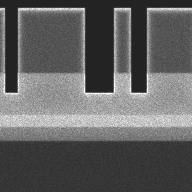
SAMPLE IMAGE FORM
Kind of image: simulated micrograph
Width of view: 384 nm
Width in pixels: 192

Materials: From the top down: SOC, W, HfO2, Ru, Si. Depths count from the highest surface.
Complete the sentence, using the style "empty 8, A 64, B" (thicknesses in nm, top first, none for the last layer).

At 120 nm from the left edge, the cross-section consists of SOC 130, W 84, HfO2 24, Ru 28, Si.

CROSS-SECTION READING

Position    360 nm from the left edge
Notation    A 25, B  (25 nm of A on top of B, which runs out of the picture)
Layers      SOC 130, W 84, HfO2 24, Ru 28, Si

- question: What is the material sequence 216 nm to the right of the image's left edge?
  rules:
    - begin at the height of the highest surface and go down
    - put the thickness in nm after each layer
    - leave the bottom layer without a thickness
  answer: empty 170, W 44, HfO2 24, Ru 28, Si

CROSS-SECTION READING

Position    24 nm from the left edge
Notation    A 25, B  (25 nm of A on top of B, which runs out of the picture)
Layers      empty 170, W 44, HfO2 24, Ru 28, Si